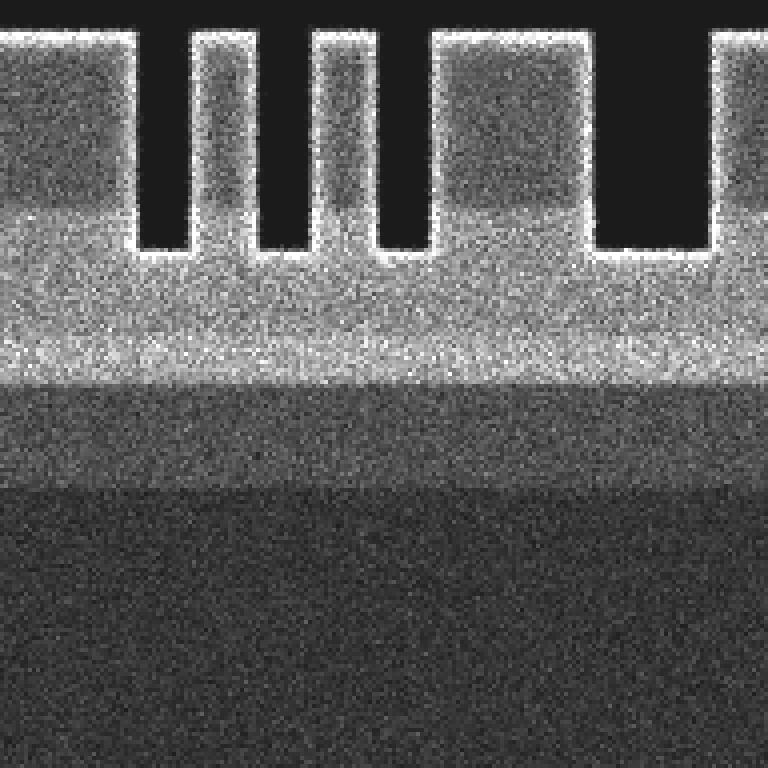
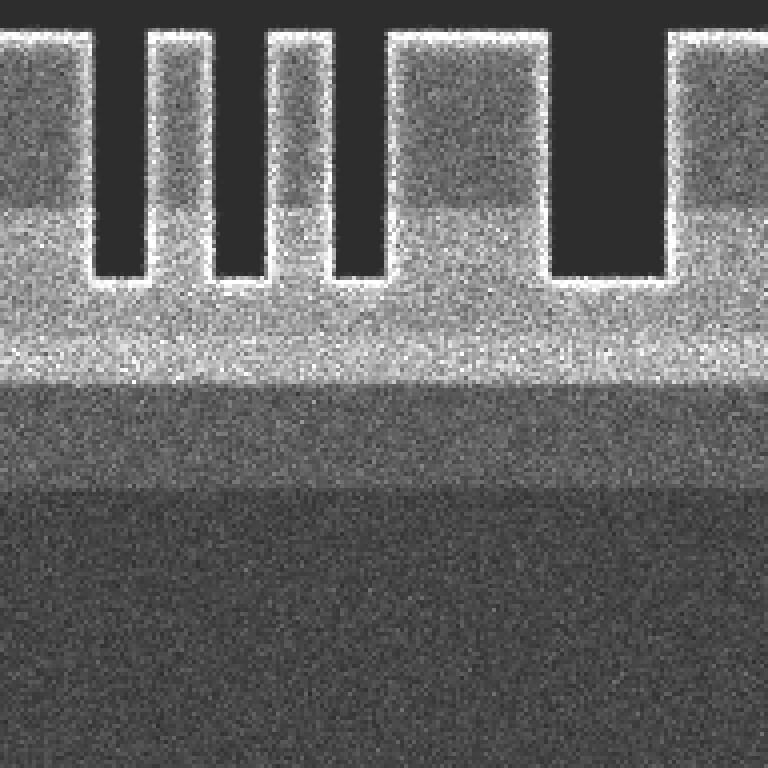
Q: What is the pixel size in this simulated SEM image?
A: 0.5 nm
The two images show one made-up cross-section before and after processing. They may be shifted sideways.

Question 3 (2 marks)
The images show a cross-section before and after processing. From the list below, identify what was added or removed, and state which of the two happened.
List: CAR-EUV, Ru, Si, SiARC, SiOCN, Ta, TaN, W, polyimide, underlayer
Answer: Ru was removed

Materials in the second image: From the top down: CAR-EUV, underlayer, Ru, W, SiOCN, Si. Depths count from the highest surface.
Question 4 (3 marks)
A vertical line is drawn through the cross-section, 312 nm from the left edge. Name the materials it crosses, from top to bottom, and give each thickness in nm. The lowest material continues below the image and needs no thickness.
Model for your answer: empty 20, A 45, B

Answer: empty 124, Ru 28, W 24, SiOCN 52, Si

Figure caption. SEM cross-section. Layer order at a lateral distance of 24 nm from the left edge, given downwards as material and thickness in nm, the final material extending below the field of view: CAR-EUV 58, underlayer 30, Ru 64, W 24, SiOCN 52, Si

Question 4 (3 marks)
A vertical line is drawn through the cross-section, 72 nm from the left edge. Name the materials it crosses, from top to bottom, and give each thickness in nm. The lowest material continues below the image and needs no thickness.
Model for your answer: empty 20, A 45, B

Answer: empty 124, Ru 28, W 24, SiOCN 52, Si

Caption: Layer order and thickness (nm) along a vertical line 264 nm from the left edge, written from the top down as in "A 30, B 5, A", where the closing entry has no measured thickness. CAR-EUV 58, underlayer 30, Ru 64, W 24, SiOCN 52, Si